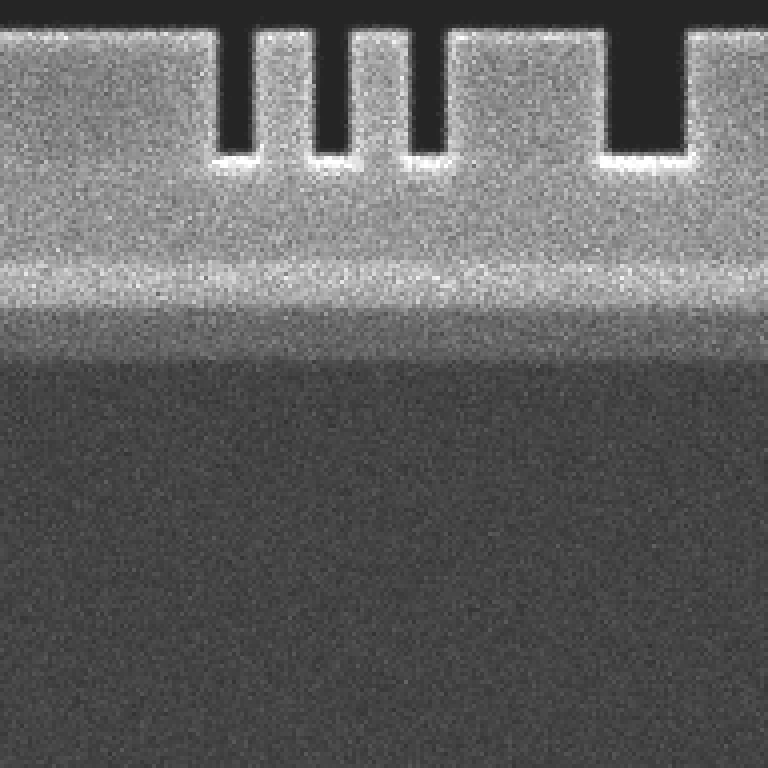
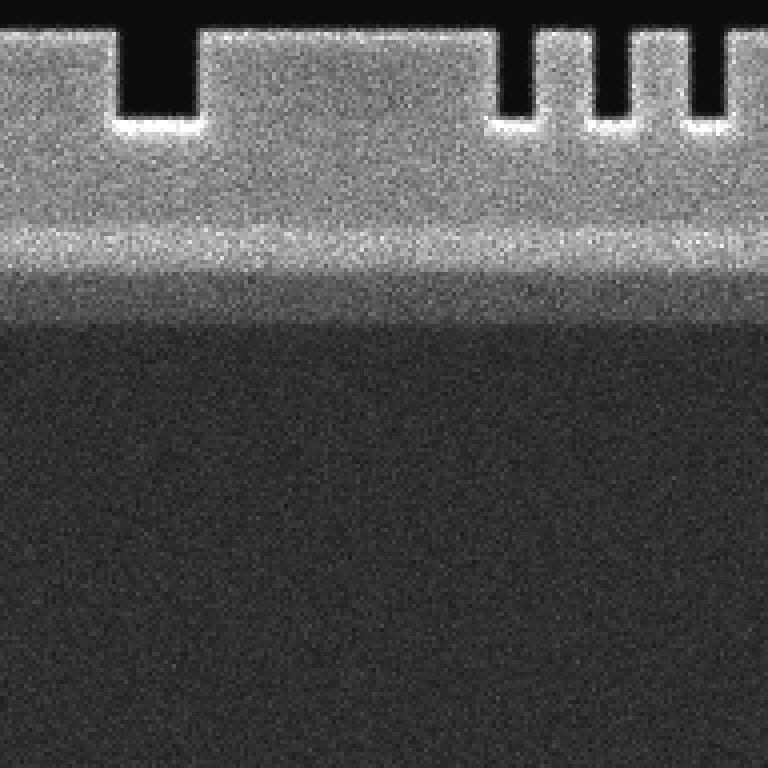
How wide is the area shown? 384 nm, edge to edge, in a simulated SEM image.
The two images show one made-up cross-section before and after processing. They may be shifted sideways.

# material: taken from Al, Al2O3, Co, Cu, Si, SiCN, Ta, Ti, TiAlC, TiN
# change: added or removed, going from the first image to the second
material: TiN
change: removed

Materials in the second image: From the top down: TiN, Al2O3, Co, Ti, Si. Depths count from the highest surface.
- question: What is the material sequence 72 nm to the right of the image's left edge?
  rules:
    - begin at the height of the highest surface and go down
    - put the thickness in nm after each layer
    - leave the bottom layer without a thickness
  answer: empty 44, Al2O3 54, Co 22, Ti 26, Si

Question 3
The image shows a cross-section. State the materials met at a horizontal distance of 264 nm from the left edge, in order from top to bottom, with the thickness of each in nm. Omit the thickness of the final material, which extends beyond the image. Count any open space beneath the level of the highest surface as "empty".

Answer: empty 44, Al2O3 54, Co 22, Ti 26, Si